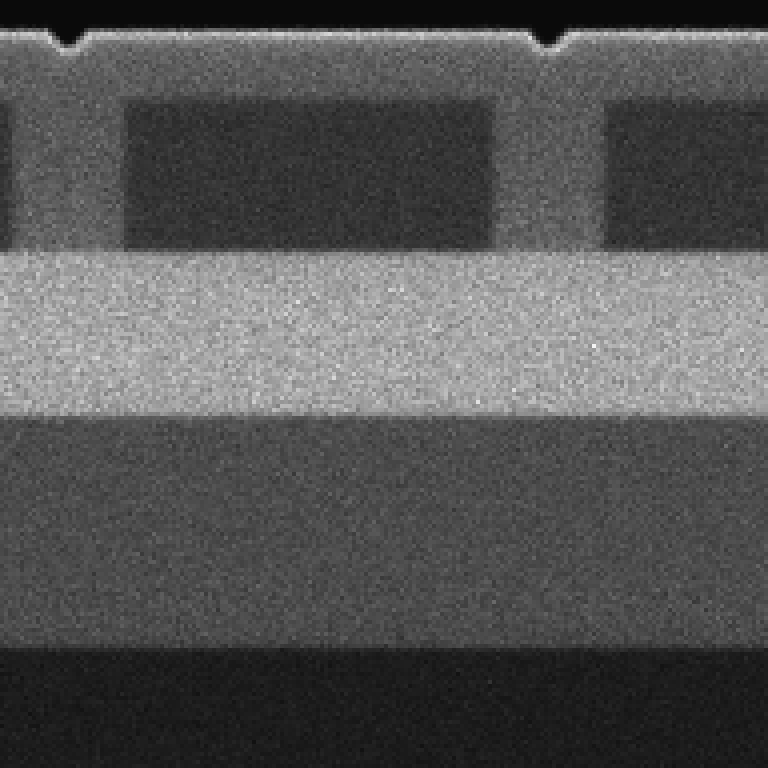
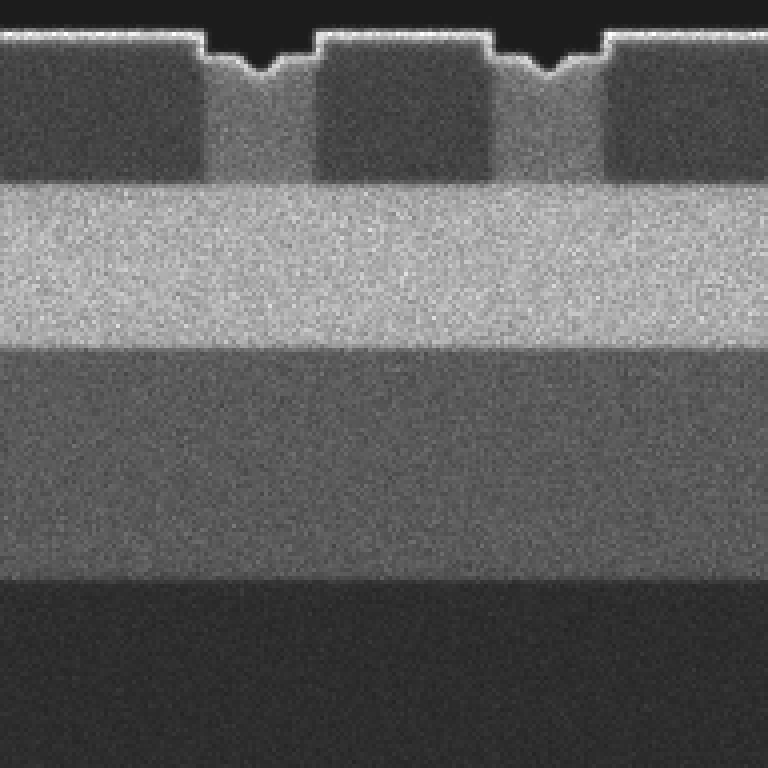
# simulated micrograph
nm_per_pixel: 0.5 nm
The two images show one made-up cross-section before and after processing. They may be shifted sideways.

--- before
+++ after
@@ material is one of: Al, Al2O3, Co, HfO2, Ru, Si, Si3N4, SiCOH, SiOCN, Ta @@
Ru removed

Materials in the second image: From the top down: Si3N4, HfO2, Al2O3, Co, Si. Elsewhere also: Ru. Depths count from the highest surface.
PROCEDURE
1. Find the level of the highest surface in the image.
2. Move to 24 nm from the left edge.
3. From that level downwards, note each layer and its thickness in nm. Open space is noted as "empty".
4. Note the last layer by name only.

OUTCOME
Si3N4 76, HfO2 82, Al2O3 86, Co 30, Si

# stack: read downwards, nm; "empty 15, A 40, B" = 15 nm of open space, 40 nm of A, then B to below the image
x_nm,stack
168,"Si3N4 76, HfO2 82, Al2O3 86, Co 30, Si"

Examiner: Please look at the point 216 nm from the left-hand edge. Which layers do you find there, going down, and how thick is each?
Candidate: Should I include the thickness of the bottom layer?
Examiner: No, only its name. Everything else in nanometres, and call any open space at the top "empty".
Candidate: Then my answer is Si3N4 76, HfO2 82, Al2O3 86, Co 30, Si